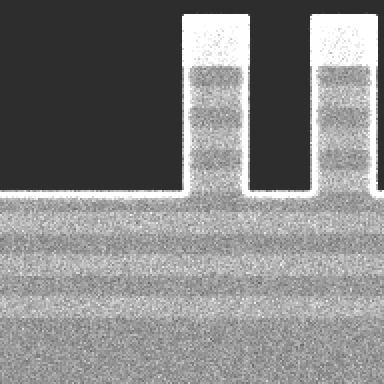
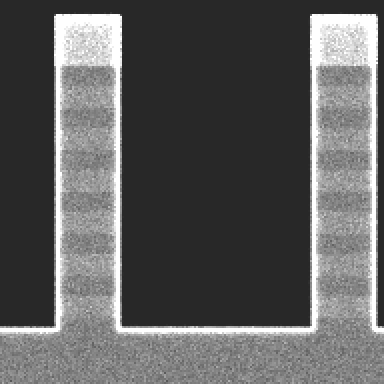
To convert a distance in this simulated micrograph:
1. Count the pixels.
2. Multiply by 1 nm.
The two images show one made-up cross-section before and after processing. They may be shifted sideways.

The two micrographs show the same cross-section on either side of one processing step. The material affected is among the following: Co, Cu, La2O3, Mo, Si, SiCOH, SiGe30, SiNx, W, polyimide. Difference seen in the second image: Si and SiGe30 removed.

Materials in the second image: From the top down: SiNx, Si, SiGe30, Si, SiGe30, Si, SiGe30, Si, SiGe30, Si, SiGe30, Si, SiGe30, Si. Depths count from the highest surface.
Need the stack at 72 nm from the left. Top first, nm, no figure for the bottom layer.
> SiNx 50, Si 20, SiGe30 22, Si 20, SiGe30 22, Si 20, SiGe30 22, Si 20, SiGe30 22, Si 20, SiGe30 22, Si 20, SiGe30 22, Si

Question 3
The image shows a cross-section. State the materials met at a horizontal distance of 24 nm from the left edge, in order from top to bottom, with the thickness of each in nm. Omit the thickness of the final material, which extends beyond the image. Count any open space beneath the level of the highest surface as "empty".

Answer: empty 312, Si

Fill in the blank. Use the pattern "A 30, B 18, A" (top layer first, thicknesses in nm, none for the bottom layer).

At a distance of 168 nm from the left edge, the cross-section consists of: empty 312, Si